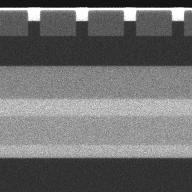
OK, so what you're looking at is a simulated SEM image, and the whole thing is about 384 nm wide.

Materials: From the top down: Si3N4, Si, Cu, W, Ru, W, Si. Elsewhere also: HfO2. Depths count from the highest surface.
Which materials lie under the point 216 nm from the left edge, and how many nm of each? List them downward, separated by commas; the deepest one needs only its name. Si3N4 56, Si 60, Cu 66, W 34, Ru 58, W 26, Si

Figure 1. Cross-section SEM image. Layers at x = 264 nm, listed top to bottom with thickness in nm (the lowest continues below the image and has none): HfO2 26, Si 90, Cu 66, W 34, Ru 58, W 26, Si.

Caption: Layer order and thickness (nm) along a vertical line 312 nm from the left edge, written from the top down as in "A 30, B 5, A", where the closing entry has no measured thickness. Si3N4 56, Si 60, Cu 66, W 34, Ru 58, W 26, Si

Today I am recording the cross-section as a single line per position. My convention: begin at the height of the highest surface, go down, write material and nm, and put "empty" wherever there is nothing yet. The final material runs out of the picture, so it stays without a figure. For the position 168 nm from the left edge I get HfO2 26, Si 90, Cu 66, W 34, Ru 58, W 26, Si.